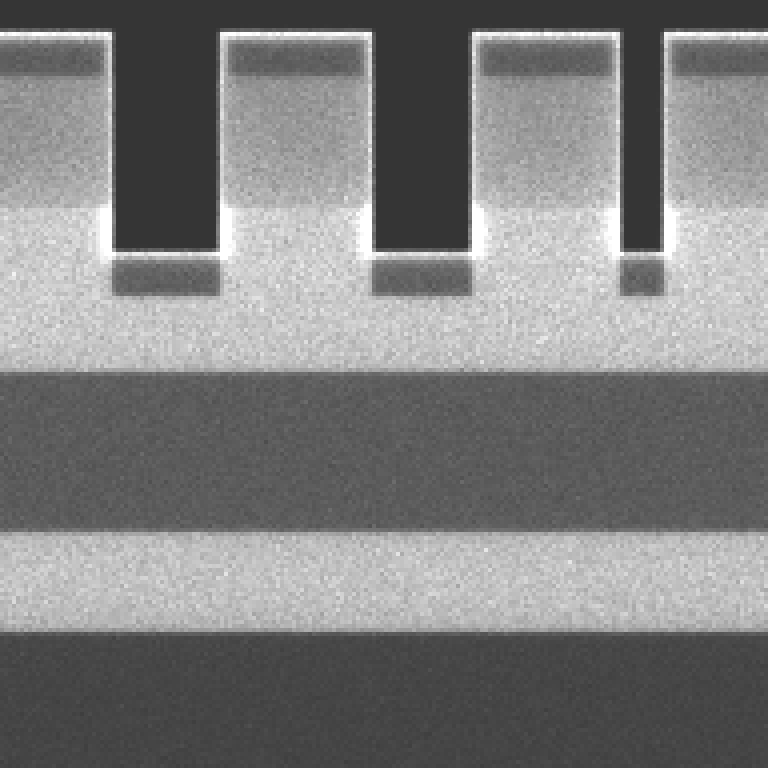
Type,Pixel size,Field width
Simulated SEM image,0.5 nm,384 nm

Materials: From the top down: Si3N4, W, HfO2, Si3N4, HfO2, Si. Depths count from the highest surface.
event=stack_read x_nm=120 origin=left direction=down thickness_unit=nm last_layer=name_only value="Si3N4 22, W 66, HfO2 82, Si3N4 80, HfO2 50, Si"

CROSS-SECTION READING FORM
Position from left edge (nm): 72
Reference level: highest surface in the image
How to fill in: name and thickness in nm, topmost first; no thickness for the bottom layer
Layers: empty 110, Si3N4 22, HfO2 38, Si3N4 80, HfO2 50, Si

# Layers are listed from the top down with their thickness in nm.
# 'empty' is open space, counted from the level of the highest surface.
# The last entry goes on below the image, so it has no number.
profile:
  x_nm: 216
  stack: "empty 110, Si3N4 22, HfO2 38, Si3N4 80, HfO2 50, Si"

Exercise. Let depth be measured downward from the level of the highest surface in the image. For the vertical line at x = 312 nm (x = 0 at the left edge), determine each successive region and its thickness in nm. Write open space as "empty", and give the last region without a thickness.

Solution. empty 110, Si3N4 22, HfO2 38, Si3N4 80, HfO2 50, Si